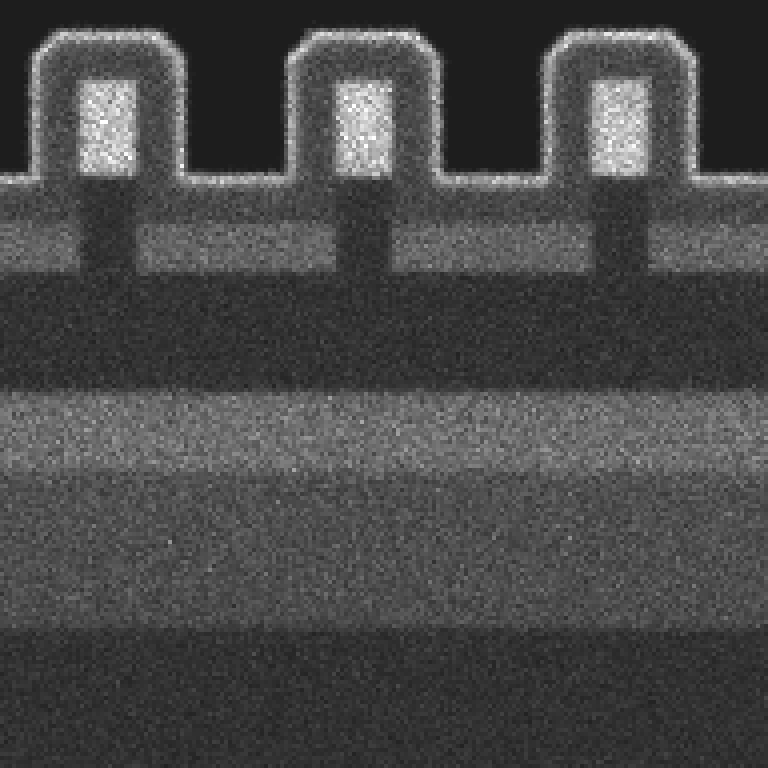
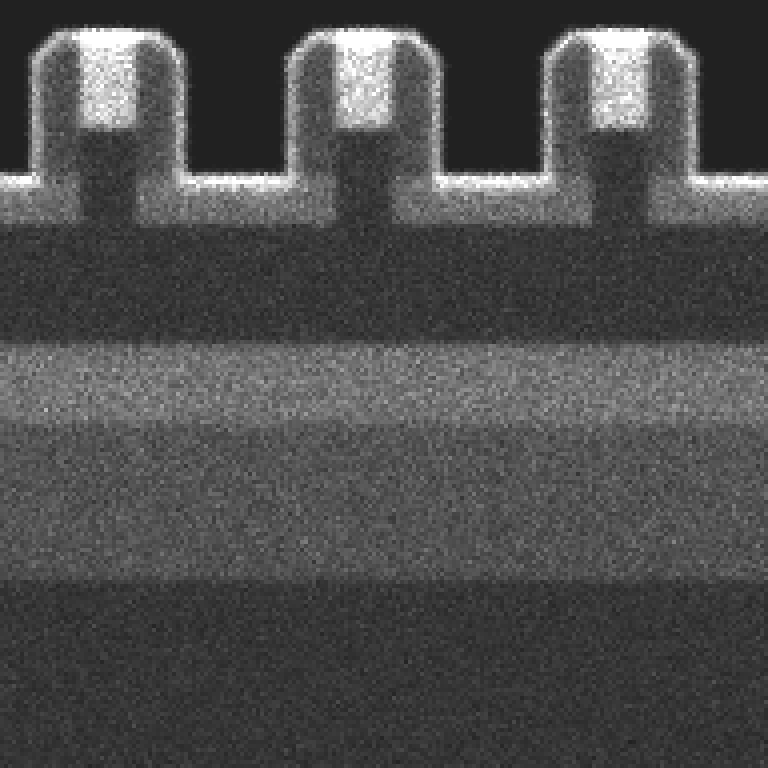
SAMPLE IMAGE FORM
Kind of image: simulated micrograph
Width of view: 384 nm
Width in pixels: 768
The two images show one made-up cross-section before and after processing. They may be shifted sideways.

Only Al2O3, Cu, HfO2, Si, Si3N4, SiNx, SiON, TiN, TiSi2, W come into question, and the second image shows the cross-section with SiNx removed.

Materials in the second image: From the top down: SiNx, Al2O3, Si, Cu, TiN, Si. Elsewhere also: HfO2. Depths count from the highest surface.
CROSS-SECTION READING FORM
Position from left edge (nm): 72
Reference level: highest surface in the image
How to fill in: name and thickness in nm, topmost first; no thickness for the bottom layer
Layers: SiNx 72, Al2O3 24, Si 60, Cu 40, TiN 78, Si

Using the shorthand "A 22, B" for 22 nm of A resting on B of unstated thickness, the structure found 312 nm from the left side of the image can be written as HfO2 48, Si 108, Cu 40, TiN 78, Si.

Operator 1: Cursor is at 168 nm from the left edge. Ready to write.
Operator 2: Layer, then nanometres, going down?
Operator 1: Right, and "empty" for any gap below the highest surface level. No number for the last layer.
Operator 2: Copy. HfO2 48, Si 108, Cu 40, TiN 78, Si